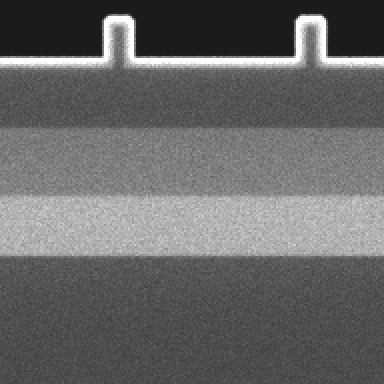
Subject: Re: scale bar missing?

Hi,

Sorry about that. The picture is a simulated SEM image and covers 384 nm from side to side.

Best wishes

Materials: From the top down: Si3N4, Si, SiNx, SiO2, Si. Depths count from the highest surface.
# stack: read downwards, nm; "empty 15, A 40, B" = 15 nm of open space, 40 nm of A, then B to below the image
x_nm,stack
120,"Si3N4 10, Si 102, SiNx 68, SiO2 60, Si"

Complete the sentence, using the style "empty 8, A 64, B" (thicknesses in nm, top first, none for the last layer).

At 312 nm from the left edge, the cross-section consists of Si3N4 10, Si 102, SiNx 68, SiO2 60, Si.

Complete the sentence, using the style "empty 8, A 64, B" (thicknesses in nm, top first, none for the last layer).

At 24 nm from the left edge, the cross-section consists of empty 42, Si3N4 10, Si 60, SiNx 68, SiO2 60, Si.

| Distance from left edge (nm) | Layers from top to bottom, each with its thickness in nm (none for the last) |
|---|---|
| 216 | empty 42, Si3N4 10, Si 60, SiNx 68, SiO2 60, Si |